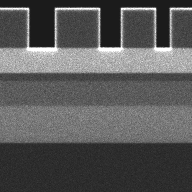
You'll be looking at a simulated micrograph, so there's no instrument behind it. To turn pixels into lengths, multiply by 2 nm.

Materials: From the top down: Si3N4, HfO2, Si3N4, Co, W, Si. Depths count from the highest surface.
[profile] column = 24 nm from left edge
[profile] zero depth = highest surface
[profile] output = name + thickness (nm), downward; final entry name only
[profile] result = Si3N4 80, HfO2 50, Si3N4 16, Co 50, W 74, Si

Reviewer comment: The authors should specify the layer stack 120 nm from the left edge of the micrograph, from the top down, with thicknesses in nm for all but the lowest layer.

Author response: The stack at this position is Si3N4 80, HfO2 50, Si3N4 16, Co 50, W 74, Si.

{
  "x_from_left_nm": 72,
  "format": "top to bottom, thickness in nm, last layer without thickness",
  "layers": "empty 80, HfO2 50, Si3N4 16, Co 50, W 74, Si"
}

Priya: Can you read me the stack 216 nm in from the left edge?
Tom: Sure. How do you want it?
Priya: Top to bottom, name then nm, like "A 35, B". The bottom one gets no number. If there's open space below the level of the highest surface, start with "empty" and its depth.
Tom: empty 80, HfO2 50, Si3N4 16, Co 50, W 74, Si